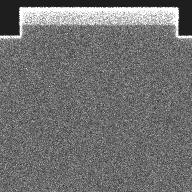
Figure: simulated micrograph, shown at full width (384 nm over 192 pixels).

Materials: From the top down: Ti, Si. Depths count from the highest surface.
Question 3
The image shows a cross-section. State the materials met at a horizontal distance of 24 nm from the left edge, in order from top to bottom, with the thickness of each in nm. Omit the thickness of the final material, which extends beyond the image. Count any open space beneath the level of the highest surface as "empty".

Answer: empty 56, Si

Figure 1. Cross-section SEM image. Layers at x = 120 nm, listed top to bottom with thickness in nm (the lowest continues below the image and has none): Ti 34, Si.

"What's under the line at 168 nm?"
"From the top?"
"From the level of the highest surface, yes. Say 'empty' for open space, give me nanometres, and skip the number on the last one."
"Ti 34, Si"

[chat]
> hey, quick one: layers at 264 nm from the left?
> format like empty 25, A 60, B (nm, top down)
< Ti 34, Si